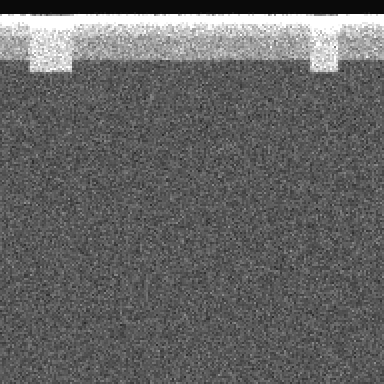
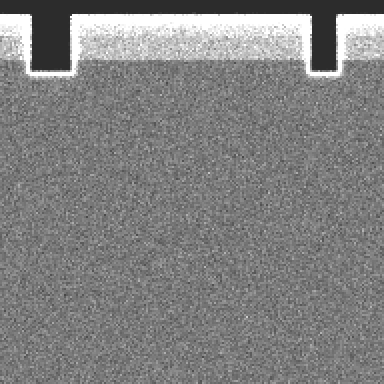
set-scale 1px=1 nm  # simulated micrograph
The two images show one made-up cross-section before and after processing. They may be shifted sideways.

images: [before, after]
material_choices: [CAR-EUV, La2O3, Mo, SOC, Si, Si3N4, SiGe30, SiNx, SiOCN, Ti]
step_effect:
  removed: SOC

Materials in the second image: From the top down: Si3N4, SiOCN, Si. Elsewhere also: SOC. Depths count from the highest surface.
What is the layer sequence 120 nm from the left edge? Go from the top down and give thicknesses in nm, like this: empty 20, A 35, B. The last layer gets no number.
Si3N4 20, SiOCN 24, Si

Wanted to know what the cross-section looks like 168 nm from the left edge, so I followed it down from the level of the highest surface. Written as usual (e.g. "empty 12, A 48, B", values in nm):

Si3N4 20, SiOCN 24, Si